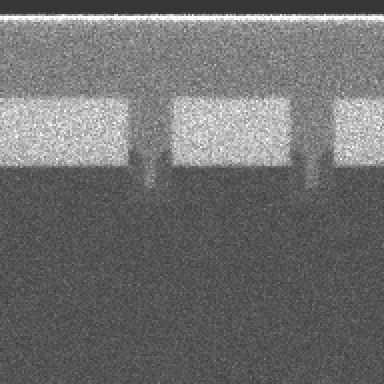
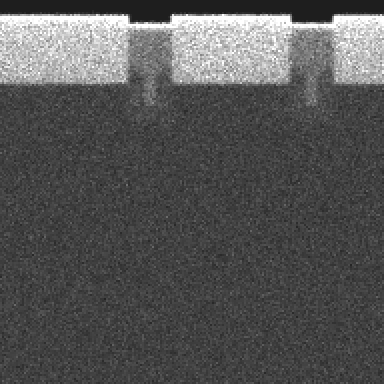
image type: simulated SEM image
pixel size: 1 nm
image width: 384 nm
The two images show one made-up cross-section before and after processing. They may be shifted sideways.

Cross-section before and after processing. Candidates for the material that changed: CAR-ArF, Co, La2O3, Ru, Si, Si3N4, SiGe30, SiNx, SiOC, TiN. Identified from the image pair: TiN (removed).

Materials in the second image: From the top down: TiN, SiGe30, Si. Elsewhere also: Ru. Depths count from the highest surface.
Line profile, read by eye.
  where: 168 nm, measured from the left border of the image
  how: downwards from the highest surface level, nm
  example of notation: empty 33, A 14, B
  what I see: empty 8, TiN 44, SiGe30 54, Si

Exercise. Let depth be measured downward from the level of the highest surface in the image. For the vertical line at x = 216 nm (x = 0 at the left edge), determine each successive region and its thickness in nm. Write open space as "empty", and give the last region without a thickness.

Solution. Ru 68, Si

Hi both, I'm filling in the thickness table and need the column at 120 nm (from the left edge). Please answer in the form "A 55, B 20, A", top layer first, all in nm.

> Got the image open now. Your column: Ru 68, Si